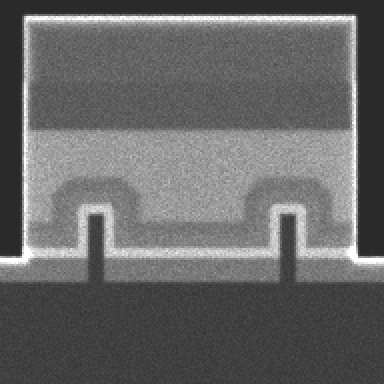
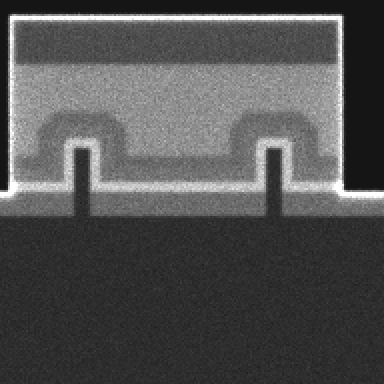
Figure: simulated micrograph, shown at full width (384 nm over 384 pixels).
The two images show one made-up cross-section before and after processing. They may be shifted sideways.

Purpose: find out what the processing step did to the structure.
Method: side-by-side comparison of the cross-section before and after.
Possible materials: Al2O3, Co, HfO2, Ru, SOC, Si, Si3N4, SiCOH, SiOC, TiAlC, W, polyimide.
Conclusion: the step removed SOC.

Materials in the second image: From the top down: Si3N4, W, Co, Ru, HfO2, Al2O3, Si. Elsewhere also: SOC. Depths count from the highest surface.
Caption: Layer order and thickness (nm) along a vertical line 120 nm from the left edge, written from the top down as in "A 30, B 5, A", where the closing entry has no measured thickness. Si3N4 48, W 60, Co 44, Ru 14, HfO2 10, Al2O3 24, Si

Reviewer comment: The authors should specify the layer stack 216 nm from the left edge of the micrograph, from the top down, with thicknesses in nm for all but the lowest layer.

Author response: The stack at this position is Si3N4 48, W 92, Co 12, Ru 14, HfO2 10, Al2O3 24, Si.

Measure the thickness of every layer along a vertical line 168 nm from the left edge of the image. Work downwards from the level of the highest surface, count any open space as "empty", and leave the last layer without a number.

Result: Si3N4 48, W 92, Co 12, Ru 14, HfO2 10, Al2O3 24, Si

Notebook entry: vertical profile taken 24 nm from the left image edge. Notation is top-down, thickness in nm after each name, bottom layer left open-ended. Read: Si3N4 48, W 92, Co 12, Ru 14, HfO2 10, Al2O3 24, Si